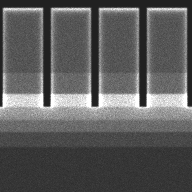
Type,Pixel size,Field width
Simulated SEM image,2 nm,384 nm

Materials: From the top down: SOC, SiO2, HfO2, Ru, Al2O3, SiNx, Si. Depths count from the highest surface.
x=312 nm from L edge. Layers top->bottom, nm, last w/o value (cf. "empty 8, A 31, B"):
SOC 130, SiO2 42, HfO2 26, Ru 26, Al2O3 24, SiNx 30, Si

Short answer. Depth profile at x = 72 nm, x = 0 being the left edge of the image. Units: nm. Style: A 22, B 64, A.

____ SOC 130, SiO2 42, HfO2 26, Ru 26, Al2O3 24, SiNx 30, Si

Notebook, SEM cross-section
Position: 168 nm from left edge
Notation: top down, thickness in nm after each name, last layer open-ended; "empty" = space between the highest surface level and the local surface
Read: SOC 130, SiO2 42, HfO2 26, Ru 26, Al2O3 24, SiNx 30, Si